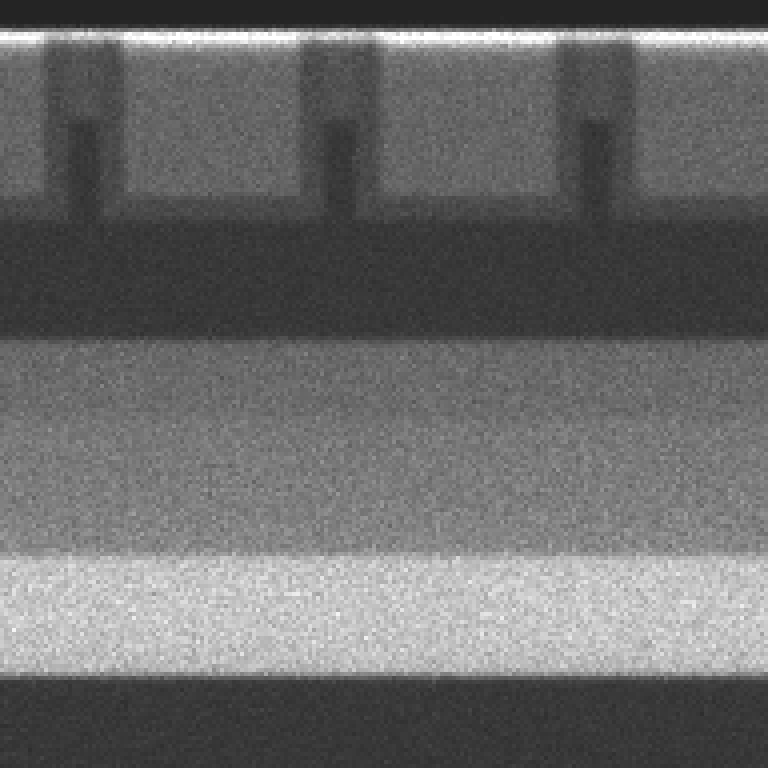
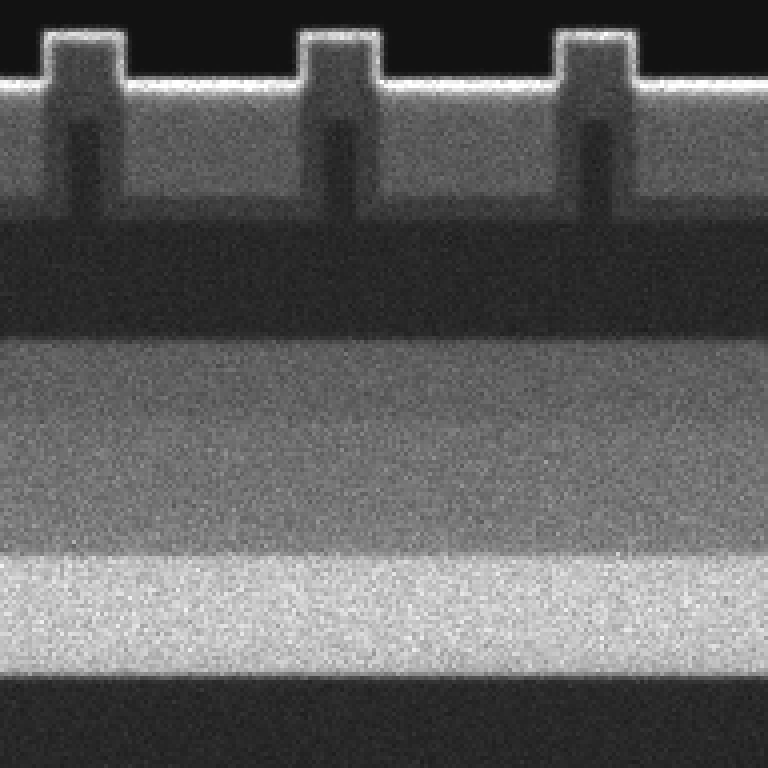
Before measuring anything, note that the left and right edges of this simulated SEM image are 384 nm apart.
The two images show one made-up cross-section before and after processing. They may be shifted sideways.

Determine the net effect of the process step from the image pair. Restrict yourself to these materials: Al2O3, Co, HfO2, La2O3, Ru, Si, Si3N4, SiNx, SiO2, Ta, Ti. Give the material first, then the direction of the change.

SiO2: removed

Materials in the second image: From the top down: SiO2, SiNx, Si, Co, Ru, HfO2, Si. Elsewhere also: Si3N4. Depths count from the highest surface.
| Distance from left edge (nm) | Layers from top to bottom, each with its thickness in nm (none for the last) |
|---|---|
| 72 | empty 24, SiO2 58, SiNx 12, Si 60, Co 40, Ru 68, HfO2 60, Si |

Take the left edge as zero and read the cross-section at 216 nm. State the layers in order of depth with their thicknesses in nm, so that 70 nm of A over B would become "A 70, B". empty 24, SiO2 58, SiNx 12, Si 60, Co 40, Ru 68, HfO2 60, Si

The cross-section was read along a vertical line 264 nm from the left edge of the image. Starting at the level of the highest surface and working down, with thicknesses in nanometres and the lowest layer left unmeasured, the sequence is empty 24, SiO2 58, SiNx 12, Si 60, Co 40, Ru 68, HfO2 60, Si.